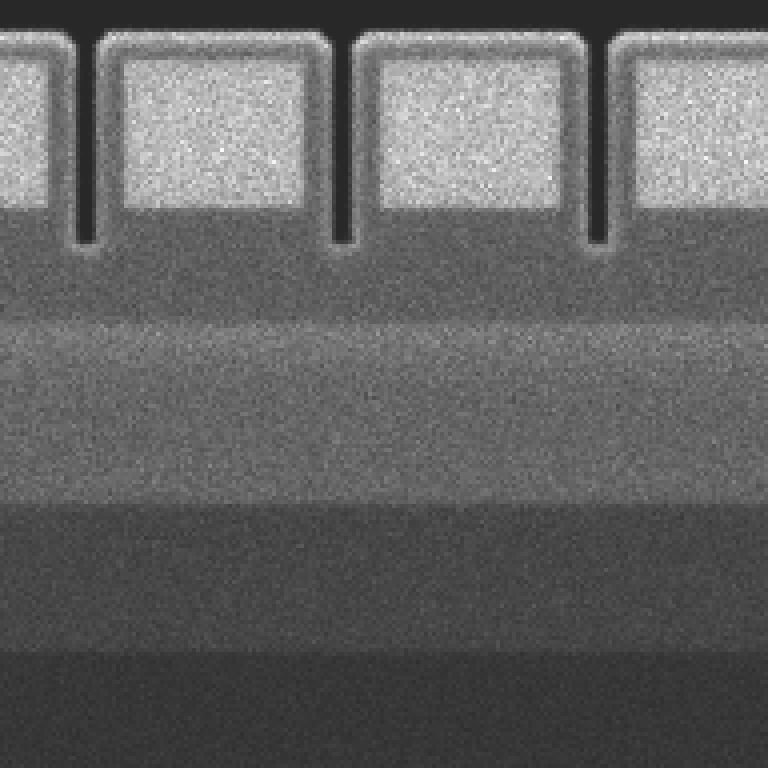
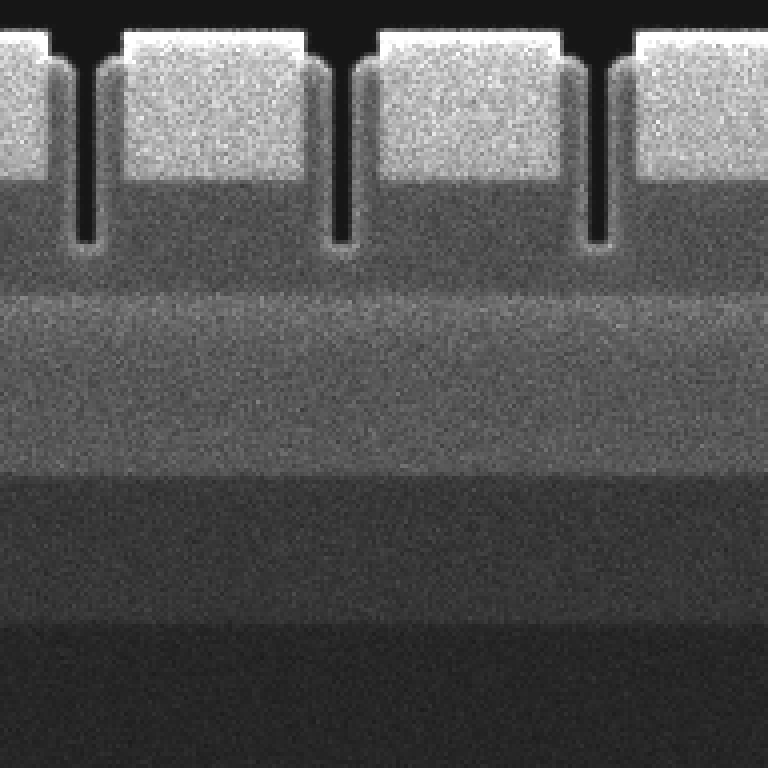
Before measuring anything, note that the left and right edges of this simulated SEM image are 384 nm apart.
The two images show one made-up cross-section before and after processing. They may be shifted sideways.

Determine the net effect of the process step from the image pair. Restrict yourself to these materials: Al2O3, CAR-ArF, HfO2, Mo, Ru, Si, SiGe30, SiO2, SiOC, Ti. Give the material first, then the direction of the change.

SiO2: removed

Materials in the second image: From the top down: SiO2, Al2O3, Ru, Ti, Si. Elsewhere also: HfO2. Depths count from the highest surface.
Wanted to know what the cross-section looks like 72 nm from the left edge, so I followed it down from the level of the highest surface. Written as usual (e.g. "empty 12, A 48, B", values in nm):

HfO2 74, Al2O3 58, Ru 90, Ti 74, Si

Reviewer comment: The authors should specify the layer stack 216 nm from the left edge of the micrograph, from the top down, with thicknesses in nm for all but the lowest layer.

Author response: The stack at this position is HfO2 74, Al2O3 58, Ru 90, Ti 74, Si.